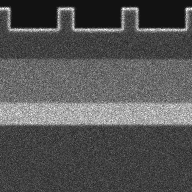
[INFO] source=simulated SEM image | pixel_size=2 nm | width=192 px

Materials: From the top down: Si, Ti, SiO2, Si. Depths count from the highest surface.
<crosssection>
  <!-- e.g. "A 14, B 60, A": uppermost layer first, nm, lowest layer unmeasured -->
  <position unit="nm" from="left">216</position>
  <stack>empty 42, Si 60, Ti 88, SiO2 44, Si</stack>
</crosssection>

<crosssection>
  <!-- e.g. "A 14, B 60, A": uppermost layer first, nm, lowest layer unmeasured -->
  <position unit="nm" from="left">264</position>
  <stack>Si 102, Ti 88, SiO2 44, Si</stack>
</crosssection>